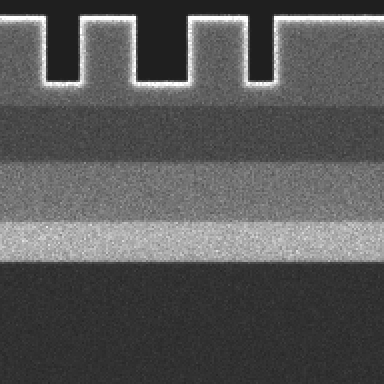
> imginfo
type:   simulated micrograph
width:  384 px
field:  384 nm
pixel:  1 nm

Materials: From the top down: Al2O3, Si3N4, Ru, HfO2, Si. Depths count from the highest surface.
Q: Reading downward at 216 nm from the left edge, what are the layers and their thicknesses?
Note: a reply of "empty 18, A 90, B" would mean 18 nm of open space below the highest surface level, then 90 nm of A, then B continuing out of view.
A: Al2O3 90, Si3N4 56, Ru 60, HfO2 40, Si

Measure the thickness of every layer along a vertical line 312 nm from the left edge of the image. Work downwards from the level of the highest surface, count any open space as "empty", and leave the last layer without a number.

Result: Al2O3 90, Si3N4 56, Ru 60, HfO2 40, Si